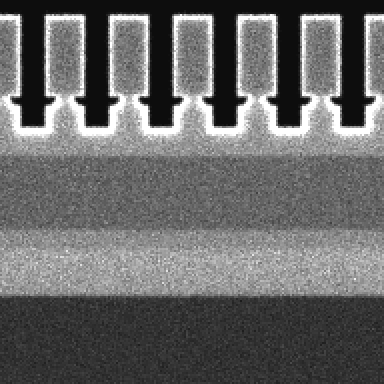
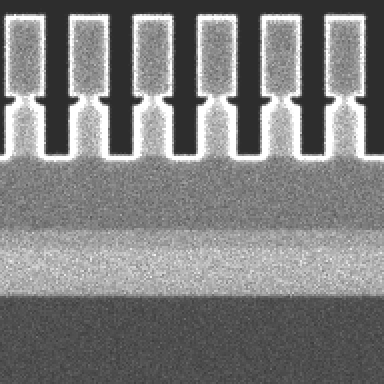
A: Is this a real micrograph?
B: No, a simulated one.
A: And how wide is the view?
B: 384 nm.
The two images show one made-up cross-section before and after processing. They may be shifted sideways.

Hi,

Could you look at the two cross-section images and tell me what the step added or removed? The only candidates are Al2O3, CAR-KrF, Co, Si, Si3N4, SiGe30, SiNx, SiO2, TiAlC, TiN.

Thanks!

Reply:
removed Al2O3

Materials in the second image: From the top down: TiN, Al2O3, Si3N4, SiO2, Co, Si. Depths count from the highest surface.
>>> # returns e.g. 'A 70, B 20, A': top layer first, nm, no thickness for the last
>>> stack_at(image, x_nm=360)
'TiN 80, empty 10, Al2O3 50, Si3N4 74, SiO2 18, Co 48, Si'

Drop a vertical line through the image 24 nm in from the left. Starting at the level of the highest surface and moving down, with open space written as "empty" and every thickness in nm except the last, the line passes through TiN 80, Al2O3 60, Si3N4 74, SiO2 18, Co 48, Si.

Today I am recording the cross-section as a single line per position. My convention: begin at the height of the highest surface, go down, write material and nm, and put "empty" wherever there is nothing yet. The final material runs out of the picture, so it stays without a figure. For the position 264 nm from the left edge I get TiN 80, empty 10, Al2O3 50, Si3N4 74, SiO2 18, Co 48, Si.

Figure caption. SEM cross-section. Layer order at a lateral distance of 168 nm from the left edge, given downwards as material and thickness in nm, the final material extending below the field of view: TiN 80, empty 10, Al2O3 50, Si3N4 74, SiO2 18, Co 48, Si